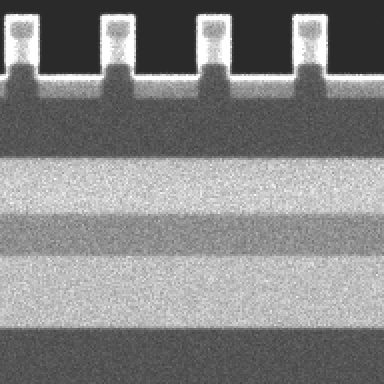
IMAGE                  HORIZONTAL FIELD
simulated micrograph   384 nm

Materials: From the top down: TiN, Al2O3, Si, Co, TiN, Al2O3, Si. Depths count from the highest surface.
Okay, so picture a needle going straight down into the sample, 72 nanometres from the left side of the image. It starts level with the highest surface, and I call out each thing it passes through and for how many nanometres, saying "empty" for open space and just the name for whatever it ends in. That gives empty 60, TiN 22, Si 60, Co 56, TiN 42, Al2O3 72, Si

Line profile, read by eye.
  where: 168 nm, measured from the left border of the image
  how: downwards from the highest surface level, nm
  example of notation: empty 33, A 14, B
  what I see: empty 60, TiN 22, Si 60, Co 56, TiN 42, Al2O3 72, Si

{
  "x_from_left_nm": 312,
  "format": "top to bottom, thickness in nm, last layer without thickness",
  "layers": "TiN 22, Al2O3 26, Si 94, Co 56, TiN 42, Al2O3 72, Si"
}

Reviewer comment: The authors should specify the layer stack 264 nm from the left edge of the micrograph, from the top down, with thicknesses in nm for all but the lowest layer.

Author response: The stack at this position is empty 60, TiN 22, Si 60, Co 56, TiN 42, Al2O3 72, Si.